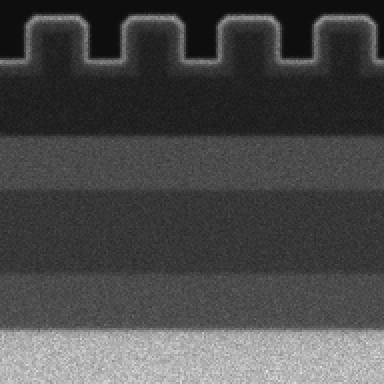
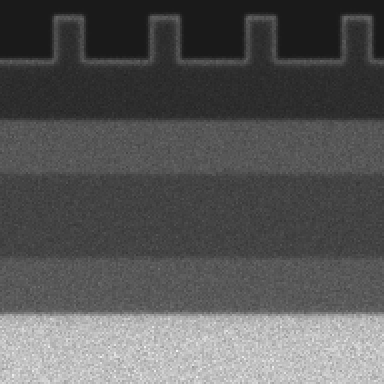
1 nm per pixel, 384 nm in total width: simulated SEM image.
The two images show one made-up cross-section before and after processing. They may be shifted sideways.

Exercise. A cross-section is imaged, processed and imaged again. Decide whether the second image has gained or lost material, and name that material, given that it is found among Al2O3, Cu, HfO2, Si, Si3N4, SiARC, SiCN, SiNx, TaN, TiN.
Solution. removed: SiNx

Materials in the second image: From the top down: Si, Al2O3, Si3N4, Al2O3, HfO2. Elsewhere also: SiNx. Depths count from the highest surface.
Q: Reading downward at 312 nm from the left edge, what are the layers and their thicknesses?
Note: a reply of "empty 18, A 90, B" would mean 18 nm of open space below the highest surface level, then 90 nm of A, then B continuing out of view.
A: empty 44, Si 60, Al2O3 54, Si3N4 84, Al2O3 56, HfO2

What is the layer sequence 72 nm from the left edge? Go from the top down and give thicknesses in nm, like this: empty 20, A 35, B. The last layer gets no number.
Si 104, Al2O3 54, Si3N4 84, Al2O3 56, HfO2